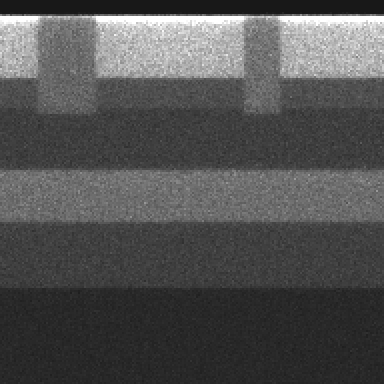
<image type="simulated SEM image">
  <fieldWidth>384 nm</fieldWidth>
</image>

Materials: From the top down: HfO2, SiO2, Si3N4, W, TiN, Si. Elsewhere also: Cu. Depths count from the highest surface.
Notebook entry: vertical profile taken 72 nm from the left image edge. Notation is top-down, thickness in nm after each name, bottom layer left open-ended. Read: Cu 98, Si3N4 56, W 52, TiN 66, Si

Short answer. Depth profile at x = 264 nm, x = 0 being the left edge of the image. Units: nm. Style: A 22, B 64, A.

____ Cu 98, Si3N4 56, W 52, TiN 66, Si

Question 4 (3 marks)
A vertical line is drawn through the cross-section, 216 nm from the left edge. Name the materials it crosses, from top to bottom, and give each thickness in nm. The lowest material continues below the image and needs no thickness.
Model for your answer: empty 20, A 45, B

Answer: HfO2 62, SiO2 30, Si3N4 62, W 52, TiN 66, Si